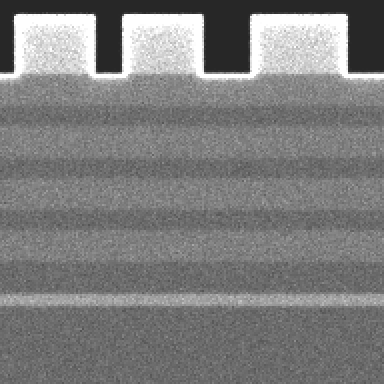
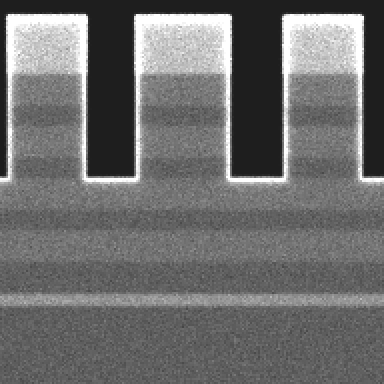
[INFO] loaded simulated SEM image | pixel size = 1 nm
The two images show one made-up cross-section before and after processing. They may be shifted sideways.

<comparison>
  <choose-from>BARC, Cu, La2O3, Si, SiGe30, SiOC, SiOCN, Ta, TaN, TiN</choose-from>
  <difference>Si and SiGe30 removed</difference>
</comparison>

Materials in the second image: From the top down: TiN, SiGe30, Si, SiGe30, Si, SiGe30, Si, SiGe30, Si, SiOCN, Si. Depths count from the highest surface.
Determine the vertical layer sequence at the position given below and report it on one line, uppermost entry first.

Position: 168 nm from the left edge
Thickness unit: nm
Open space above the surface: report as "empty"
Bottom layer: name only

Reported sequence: TiN 58, SiGe30 32, Si 20, SiGe30 32, Si 20, SiGe30 32, Si 20, SiGe30 32, Si 32, SiOCN 12, Si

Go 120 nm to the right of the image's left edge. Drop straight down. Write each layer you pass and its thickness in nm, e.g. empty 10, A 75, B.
empty 162, SiGe30 32, Si 20, SiGe30 32, Si 32, SiOCN 12, Si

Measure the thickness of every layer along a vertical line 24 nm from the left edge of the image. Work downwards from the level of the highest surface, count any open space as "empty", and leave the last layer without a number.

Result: TiN 58, SiGe30 32, Si 20, SiGe30 32, Si 20, SiGe30 32, Si 20, SiGe30 32, Si 32, SiOCN 12, Si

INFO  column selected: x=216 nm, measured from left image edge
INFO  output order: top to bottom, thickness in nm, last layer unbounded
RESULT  TiN 58, SiGe30 32, Si 20, SiGe30 32, Si 20, SiGe30 32, Si 20, SiGe30 32, Si 32, SiOCN 12, Si